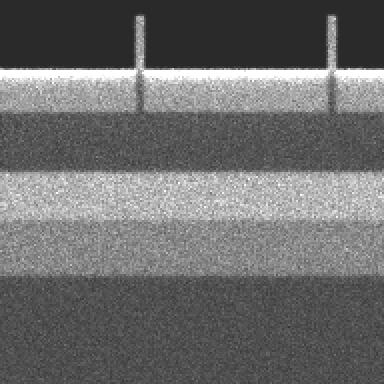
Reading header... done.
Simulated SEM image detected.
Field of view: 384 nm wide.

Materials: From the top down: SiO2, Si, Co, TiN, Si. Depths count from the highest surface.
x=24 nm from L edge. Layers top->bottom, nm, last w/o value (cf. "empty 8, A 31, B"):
empty 54, SiO2 42, Si 60, Co 48, TiN 56, Si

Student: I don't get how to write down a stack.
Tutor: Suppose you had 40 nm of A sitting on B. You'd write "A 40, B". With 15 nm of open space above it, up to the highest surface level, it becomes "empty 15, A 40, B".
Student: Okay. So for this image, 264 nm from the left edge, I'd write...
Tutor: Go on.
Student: empty 54, SiO2 42, Si 60, Co 48, TiN 56, Si